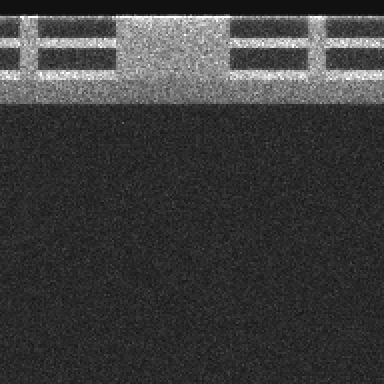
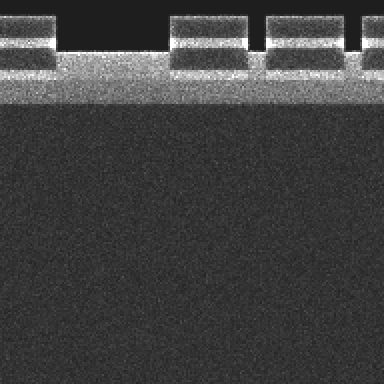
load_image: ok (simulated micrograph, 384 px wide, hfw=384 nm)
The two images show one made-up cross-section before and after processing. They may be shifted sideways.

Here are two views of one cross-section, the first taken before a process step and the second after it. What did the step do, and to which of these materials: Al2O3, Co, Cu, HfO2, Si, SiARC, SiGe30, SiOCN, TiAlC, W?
It removed W.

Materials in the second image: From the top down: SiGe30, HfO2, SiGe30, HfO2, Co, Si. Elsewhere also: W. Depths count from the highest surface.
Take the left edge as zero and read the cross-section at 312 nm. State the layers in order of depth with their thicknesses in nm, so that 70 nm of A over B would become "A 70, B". SiGe30 22, HfO2 10, SiGe30 22, HfO2 10, Co 24, Si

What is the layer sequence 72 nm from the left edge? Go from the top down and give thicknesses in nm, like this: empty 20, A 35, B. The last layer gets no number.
empty 36, W 28, Co 24, Si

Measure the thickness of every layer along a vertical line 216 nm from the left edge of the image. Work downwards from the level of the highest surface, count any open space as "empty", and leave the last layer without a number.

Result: SiGe30 22, HfO2 10, SiGe30 22, HfO2 10, Co 24, Si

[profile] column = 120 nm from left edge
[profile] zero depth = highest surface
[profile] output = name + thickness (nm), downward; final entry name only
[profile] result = empty 36, W 28, Co 24, Si